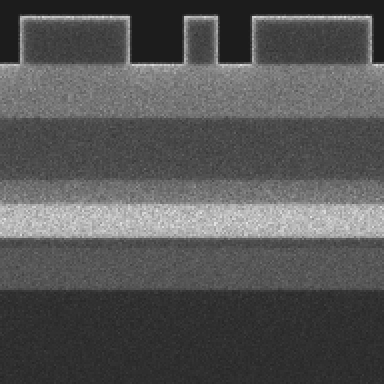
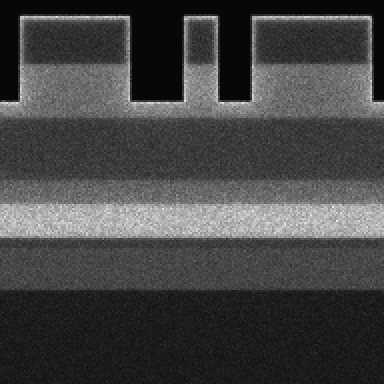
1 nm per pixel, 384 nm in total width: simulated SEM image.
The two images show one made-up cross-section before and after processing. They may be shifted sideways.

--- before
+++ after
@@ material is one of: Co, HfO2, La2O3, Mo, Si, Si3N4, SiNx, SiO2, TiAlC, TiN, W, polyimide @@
W removed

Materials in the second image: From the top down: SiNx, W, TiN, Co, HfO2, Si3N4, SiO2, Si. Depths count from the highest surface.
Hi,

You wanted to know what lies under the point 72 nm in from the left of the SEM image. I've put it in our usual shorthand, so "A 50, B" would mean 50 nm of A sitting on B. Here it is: SiNx 48, W 54, TiN 62, Co 24, HfO2 34, Si3N4 10, SiO2 42, Si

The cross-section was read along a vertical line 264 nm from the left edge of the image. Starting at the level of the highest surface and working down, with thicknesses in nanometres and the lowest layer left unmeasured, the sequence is SiNx 48, W 54, TiN 62, Co 24, HfO2 34, Si3N4 10, SiO2 42, Si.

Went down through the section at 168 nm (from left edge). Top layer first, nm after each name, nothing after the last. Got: empty 86, W 16, TiN 62, Co 24, HfO2 34, Si3N4 10, SiO2 42, Si